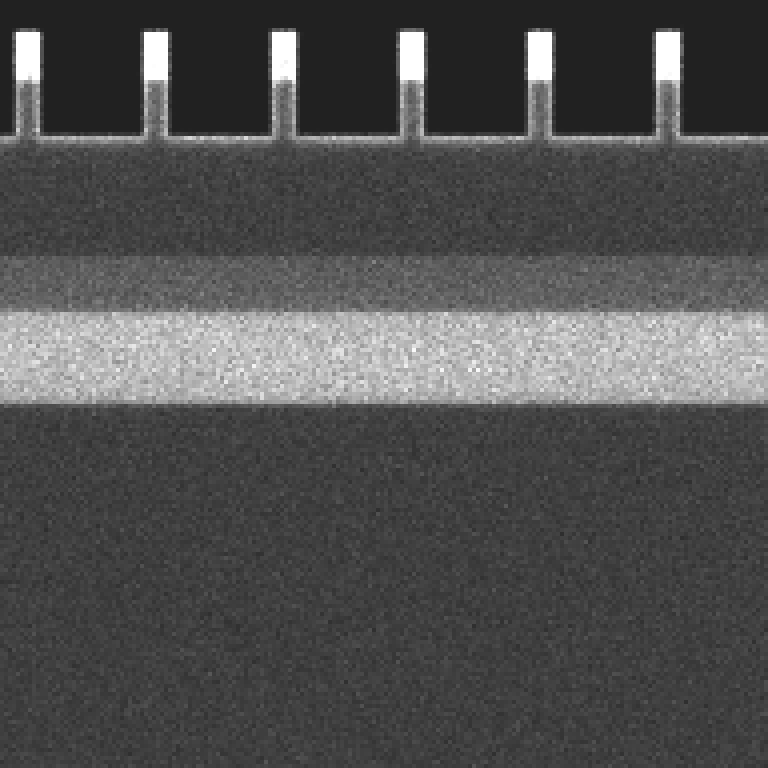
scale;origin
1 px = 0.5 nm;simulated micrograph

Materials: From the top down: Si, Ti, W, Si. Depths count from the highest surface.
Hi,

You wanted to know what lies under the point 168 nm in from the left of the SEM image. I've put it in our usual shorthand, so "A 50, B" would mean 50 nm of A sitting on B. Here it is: empty 52, Si 60, Ti 28, W 46, Si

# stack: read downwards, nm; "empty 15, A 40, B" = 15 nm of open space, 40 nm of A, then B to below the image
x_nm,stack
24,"empty 52, Si 60, Ti 28, W 46, Si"